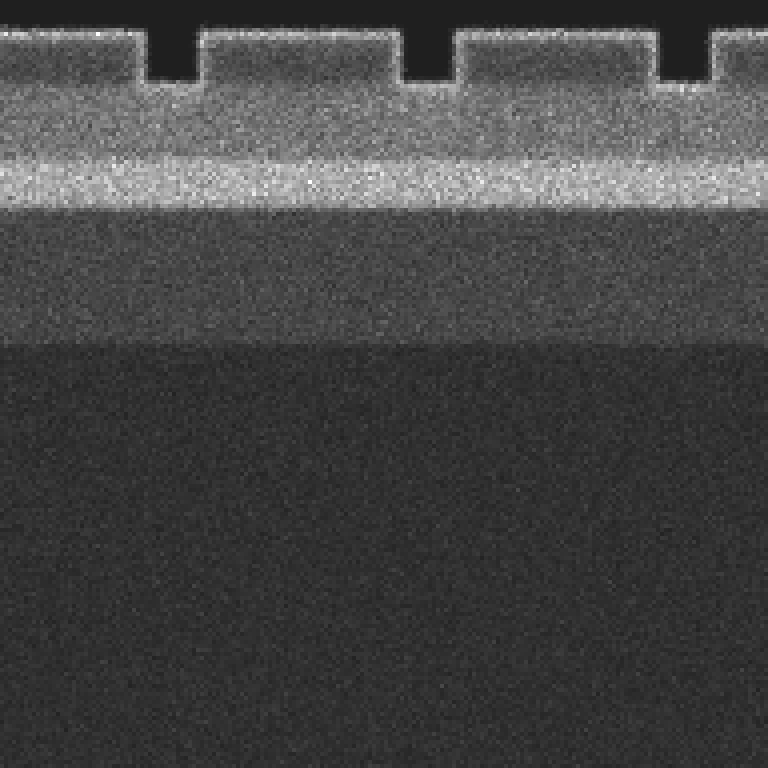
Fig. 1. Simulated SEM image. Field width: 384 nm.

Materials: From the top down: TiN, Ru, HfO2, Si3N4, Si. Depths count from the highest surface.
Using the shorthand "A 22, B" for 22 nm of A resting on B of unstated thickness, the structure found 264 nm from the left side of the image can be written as TiN 26, Ru 38, HfO2 24, Si3N4 68, Si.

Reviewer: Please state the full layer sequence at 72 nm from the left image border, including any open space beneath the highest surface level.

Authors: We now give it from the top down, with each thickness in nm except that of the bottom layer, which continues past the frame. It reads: empty 26, Ru 38, HfO2 24, Si3N4 68, Si